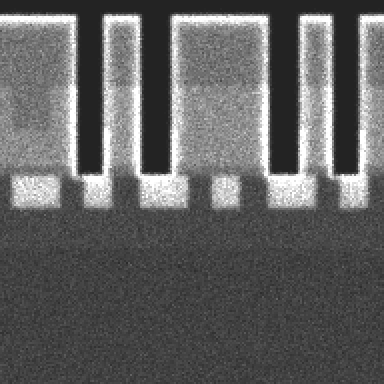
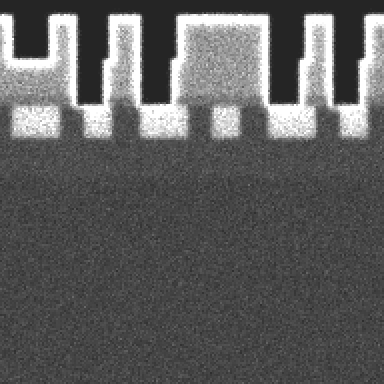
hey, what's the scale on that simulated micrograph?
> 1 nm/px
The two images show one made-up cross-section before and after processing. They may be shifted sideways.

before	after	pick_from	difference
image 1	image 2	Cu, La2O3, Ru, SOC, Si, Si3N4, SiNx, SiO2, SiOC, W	SOC removed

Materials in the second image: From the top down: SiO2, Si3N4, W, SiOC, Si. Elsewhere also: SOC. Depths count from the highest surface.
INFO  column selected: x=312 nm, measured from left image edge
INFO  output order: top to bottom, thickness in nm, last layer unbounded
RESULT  SiO2 80, Si3N4 10, W 32, SiOC 40, Si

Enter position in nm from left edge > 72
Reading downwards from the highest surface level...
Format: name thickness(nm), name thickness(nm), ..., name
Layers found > SiO2 80, Si3N4 10, SiOC 72, Si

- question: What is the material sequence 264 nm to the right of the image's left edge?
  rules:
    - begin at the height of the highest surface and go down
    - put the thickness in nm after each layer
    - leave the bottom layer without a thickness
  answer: SiO2 80, Si3N4 10, SiOC 72, Si